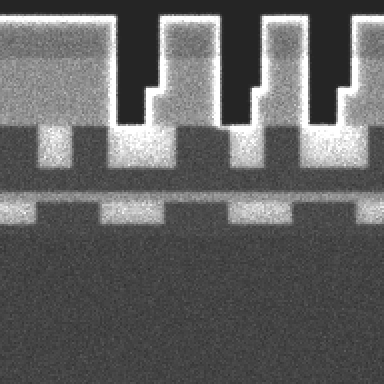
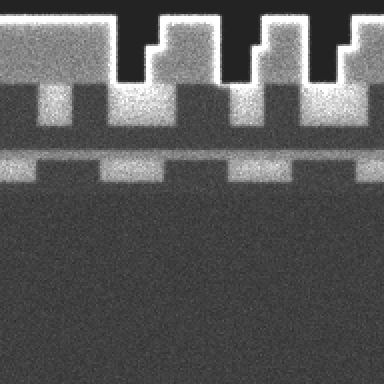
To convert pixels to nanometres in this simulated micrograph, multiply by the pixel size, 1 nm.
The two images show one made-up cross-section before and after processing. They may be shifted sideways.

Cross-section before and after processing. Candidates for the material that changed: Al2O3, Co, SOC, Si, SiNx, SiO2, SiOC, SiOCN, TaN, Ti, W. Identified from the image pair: SOC (removed).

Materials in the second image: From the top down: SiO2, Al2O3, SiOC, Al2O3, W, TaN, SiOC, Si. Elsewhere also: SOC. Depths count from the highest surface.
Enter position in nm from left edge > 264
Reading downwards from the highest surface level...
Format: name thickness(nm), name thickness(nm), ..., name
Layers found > SiO2 54, Al2O3 14, SiOC 66, Al2O3 10, W 12, TaN 10, SiOC 12, Si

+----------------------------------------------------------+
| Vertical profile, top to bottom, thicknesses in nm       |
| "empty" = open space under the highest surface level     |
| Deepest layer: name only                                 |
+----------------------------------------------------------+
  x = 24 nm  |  SiO2 54, Al2O3 14, SiOC 66, Al2O3 10, W 12, TaN 10, SiOC 12, Si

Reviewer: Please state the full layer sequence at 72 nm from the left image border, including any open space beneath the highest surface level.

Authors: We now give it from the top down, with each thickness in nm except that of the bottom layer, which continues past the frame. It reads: SiO2 54, Al2O3 14, SiOC 66, Al2O3 10, SiOC 34, Si